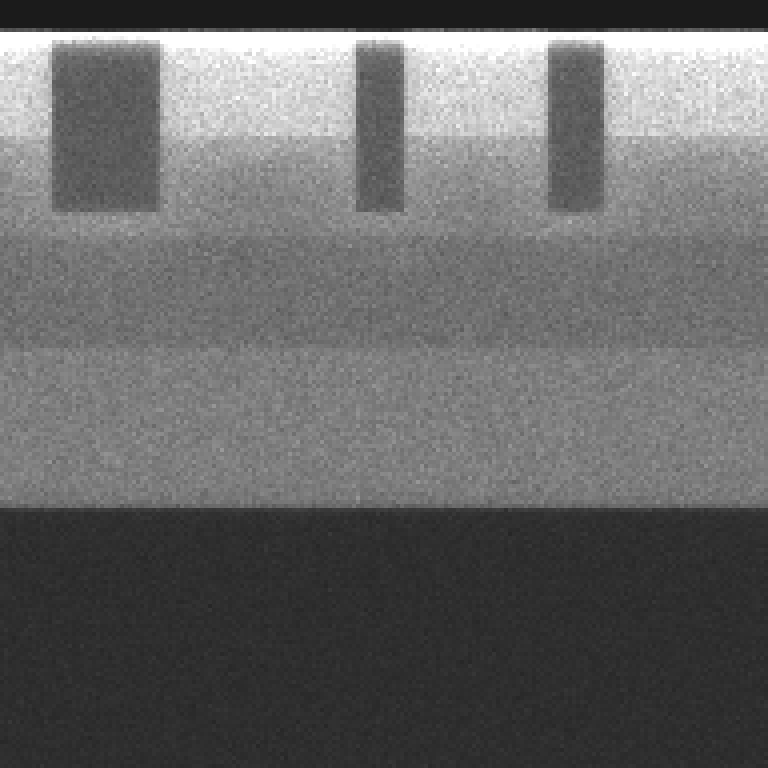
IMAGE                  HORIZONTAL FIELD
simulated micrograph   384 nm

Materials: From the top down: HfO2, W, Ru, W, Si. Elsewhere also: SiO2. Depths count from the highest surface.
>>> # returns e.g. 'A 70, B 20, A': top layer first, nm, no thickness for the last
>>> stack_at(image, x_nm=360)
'HfO2 52, W 50, Ru 56, W 80, Si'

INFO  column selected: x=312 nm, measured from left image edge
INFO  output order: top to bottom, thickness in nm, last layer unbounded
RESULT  HfO2 52, W 50, Ru 56, W 80, Si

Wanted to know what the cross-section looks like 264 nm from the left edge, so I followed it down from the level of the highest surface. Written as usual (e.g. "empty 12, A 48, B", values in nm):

HfO2 52, W 50, Ru 56, W 80, Si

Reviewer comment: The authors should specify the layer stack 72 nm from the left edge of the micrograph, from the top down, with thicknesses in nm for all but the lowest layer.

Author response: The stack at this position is SiO2 90, W 12, Ru 56, W 80, Si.